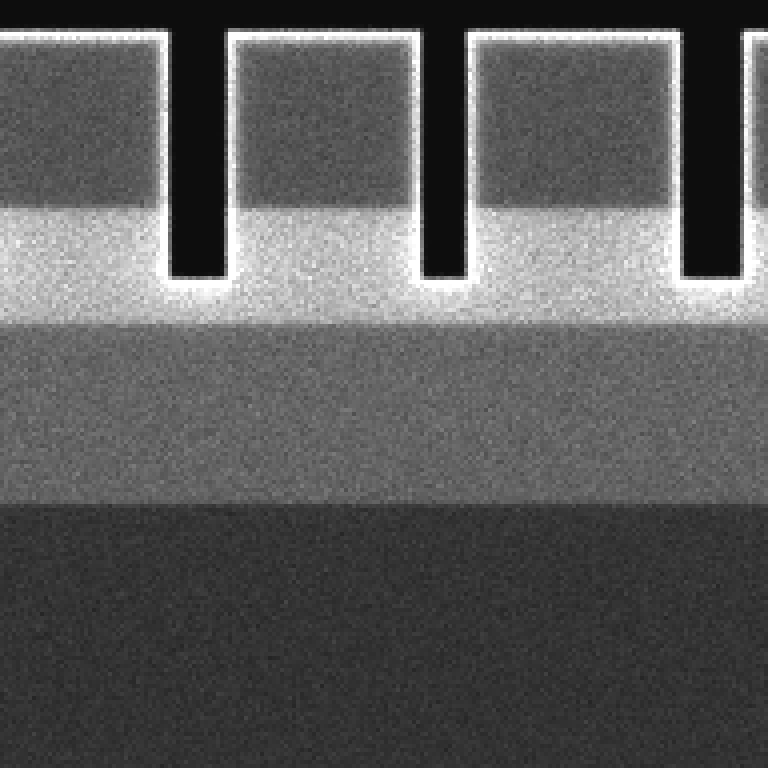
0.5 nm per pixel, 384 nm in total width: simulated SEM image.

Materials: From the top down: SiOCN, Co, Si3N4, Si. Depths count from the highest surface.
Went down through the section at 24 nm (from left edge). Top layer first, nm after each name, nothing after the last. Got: SiOCN 88, Co 58, Si3N4 90, Si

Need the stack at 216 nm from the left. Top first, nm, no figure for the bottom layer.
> empty 124, Co 22, Si3N4 90, Si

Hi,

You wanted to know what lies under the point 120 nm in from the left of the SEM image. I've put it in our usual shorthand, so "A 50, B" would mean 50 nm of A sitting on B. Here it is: SiOCN 88, Co 58, Si3N4 90, Si